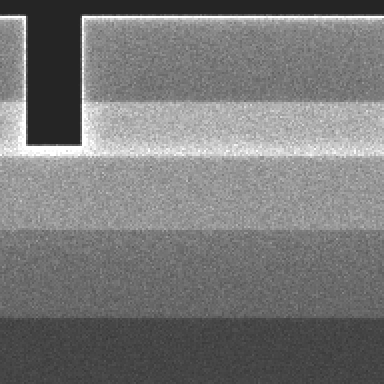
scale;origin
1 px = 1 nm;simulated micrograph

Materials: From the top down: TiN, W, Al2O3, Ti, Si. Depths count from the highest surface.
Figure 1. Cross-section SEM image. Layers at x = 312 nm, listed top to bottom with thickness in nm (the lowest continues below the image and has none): TiN 86, W 54, Al2O3 74, Ti 88, Si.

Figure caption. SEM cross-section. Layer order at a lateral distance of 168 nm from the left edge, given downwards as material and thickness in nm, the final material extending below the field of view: TiN 86, W 54, Al2O3 74, Ti 88, Si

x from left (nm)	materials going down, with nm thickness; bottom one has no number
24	TiN 86, W 54, Al2O3 74, Ti 88, Si